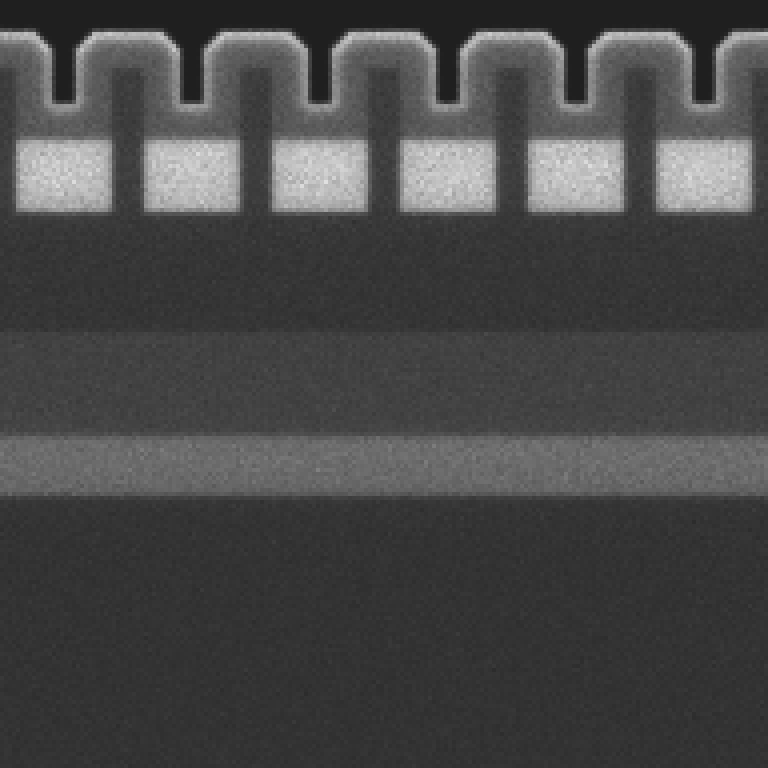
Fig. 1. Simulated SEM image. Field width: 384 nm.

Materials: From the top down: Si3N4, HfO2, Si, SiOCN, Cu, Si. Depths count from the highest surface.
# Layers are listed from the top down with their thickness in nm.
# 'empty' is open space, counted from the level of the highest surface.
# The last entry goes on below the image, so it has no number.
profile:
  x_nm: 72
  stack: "Si3N4 54, HfO2 36, Si 60, SiOCN 52, Cu 30, Si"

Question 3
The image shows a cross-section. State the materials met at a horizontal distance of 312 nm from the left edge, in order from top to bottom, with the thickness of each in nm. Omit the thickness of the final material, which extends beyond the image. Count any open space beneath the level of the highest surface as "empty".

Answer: Si3N4 18, Si 132, SiOCN 52, Cu 30, Si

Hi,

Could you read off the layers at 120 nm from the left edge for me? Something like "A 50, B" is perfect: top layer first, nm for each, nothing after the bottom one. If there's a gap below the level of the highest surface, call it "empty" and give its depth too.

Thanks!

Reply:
Si3N4 18, Si 132, SiOCN 52, Cu 30, Si